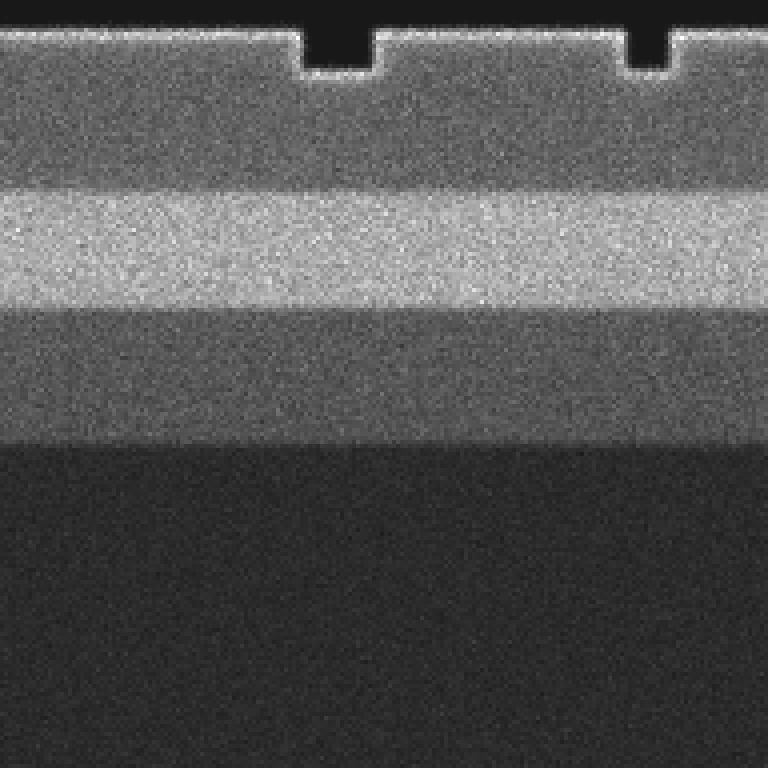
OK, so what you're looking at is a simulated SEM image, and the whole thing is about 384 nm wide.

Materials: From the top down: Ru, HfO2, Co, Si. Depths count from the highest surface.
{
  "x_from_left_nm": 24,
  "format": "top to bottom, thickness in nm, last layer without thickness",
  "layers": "Ru 80, HfO2 58, Co 68, Si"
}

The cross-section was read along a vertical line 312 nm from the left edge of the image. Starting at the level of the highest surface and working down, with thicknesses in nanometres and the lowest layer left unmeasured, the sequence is empty 20, Ru 60, HfO2 58, Co 68, Si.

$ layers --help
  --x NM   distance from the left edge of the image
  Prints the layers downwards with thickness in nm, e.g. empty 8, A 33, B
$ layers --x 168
empty 20, Ru 60, HfO2 58, Co 68, Si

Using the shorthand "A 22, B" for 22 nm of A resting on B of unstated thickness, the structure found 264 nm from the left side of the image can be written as Ru 80, HfO2 58, Co 68, Si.